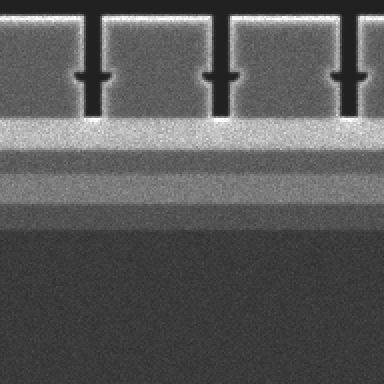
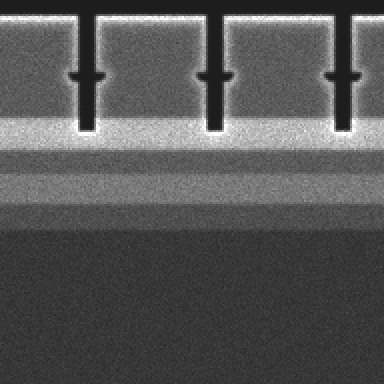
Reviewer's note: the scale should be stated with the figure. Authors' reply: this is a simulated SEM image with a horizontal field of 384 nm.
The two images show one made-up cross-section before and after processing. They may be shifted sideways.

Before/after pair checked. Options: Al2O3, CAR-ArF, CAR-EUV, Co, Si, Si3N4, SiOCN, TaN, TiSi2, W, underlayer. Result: removed W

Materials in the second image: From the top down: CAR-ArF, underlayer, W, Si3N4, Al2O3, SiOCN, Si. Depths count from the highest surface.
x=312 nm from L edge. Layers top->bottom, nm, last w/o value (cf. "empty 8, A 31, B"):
CAR-ArF 56, underlayer 46, W 32, Si3N4 24, Al2O3 30, SiOCN 26, Si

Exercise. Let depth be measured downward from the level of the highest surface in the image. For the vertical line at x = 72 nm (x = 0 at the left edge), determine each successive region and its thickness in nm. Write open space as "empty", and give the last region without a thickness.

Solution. CAR-ArF 56, empty 10, underlayer 36, W 32, Si3N4 24, Al2O3 30, SiOCN 26, Si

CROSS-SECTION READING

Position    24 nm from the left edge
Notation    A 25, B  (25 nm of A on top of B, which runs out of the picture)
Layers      CAR-ArF 56, underlayer 46, W 32, Si3N4 24, Al2O3 30, SiOCN 26, Si